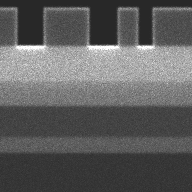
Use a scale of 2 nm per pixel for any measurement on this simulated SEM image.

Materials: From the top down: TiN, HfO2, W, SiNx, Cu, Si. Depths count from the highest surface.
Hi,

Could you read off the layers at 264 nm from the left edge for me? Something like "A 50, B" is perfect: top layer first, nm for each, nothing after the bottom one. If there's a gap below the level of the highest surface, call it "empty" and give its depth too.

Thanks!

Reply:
TiN 76, HfO2 70, W 50, SiNx 62, Cu 32, Si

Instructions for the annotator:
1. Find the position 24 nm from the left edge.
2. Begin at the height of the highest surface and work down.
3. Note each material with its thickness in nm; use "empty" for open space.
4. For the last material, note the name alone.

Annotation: TiN 76, HfO2 70, W 50, SiNx 62, Cu 32, Si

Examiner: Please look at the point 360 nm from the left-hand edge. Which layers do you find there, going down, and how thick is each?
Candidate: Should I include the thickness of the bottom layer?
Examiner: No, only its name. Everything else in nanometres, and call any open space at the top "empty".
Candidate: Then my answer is TiN 76, HfO2 70, W 50, SiNx 62, Cu 32, Si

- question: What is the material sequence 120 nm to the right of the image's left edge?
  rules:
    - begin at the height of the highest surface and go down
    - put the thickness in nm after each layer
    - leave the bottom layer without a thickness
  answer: TiN 76, HfO2 70, W 50, SiNx 62, Cu 32, Si